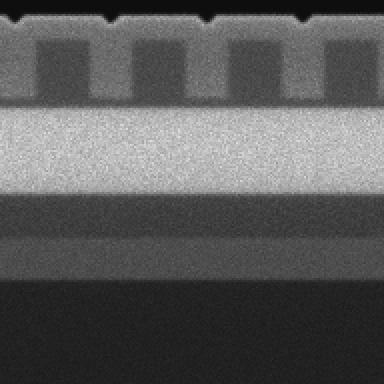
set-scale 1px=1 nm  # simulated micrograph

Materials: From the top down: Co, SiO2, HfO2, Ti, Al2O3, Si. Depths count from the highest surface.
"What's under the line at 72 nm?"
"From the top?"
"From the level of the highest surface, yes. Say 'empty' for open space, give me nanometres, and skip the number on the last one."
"Co 24, SiO2 68, HfO2 86, Ti 44, Al2O3 42, Si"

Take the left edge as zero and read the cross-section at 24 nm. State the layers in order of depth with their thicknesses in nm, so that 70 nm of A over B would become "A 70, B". Co 82, SiO2 10, HfO2 86, Ti 44, Al2O3 42, Si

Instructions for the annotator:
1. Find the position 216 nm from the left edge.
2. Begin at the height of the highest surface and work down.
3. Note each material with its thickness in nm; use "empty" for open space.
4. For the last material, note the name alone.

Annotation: Co 82, SiO2 10, HfO2 86, Ti 44, Al2O3 42, Si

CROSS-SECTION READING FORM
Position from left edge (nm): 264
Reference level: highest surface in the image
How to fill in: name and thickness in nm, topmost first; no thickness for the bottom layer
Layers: Co 24, SiO2 68, HfO2 86, Ti 44, Al2O3 42, Si